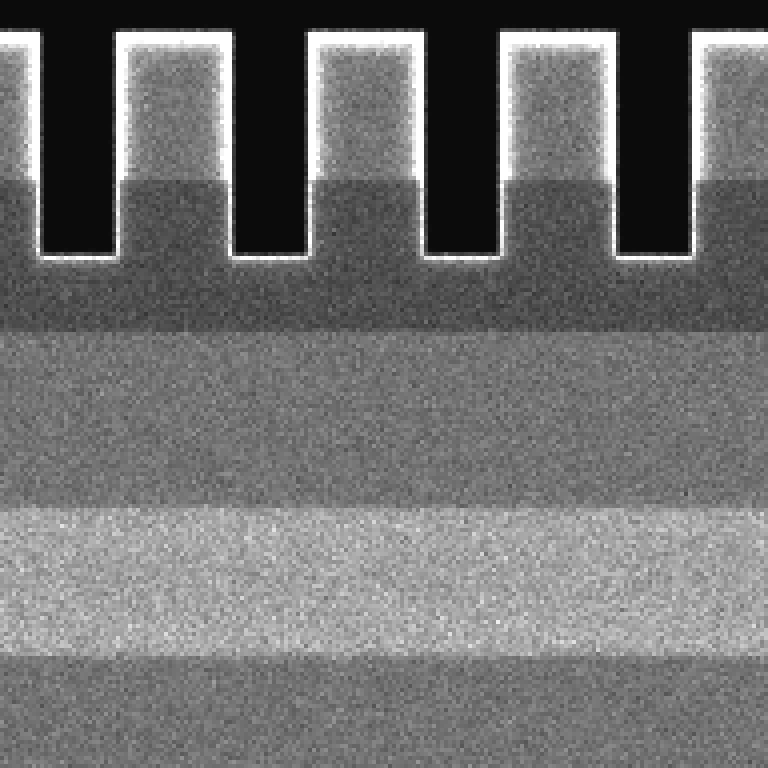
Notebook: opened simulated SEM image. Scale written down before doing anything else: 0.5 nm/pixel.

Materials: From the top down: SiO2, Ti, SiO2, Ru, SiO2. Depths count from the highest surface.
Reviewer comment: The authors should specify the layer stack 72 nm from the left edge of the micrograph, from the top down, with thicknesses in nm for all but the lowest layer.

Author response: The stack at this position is SiO2 74, Ti 76, SiO2 88, Ru 74, SiO2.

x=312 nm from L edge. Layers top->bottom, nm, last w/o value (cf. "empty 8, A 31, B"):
empty 112, Ti 38, SiO2 88, Ru 74, SiO2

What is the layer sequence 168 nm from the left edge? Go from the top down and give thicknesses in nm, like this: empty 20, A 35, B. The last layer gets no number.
SiO2 74, Ti 76, SiO2 88, Ru 74, SiO2